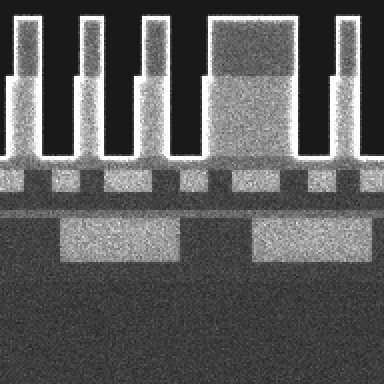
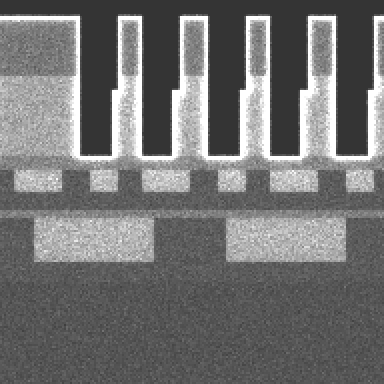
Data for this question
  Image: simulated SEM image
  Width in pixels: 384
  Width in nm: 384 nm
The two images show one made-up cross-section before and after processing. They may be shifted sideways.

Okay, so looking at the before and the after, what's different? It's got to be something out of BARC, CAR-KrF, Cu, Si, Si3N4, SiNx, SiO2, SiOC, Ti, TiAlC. SiO2, removed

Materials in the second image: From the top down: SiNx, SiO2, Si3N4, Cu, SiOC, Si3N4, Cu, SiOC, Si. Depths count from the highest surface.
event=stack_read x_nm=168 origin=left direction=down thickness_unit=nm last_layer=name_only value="empty 140, Si3N4 14, Cu 22, SiOC 18, Si3N4 8, SiOC 64, Si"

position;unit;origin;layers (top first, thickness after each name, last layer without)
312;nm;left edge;SiNx 60, SiO2 80, Si3N4 14, Cu 22, SiOC 18, Si3N4 8, Cu 44, SiOC 20, Si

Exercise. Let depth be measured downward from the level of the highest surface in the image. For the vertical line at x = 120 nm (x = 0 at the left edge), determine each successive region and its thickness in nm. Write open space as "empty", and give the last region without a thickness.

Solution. SiNx 60, SiO2 80, Si3N4 14, SiOC 40, Si3N4 8, Cu 44, SiOC 20, Si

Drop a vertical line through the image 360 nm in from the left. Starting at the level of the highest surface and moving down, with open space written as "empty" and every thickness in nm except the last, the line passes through empty 140, Si3N4 14, Cu 22, SiOC 18, Si3N4 8, SiOC 64, Si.